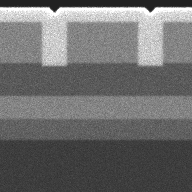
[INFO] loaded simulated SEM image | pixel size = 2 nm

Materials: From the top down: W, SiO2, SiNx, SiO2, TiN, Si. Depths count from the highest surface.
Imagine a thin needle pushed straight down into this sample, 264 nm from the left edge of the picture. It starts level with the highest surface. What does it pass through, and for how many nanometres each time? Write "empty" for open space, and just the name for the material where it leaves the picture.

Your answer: W 28, SiO2 82, SiNx 66, SiO2 46, TiN 42, Si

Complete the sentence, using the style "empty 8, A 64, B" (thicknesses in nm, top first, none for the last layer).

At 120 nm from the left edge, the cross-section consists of W 116, SiNx 60, SiO2 46, TiN 42, Si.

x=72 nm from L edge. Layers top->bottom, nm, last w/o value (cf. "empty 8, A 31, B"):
W 28, SiO2 82, SiNx 66, SiO2 46, TiN 42, Si